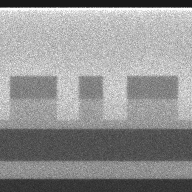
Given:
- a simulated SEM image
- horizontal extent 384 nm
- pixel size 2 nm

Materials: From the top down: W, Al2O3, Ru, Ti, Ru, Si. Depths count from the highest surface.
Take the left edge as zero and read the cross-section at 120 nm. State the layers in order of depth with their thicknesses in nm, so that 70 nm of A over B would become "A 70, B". W 224, Ru 18, Ti 64, Ru 36, Si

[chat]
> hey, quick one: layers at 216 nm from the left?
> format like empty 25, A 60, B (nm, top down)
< W 224, Ru 18, Ti 64, Ru 36, Si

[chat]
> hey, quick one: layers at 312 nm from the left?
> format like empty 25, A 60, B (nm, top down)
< W 136, Al2O3 46, Ru 60, Ti 64, Ru 36, Si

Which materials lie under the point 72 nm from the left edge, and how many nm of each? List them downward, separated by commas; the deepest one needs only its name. W 136, Al2O3 46, Ru 60, Ti 64, Ru 36, Si